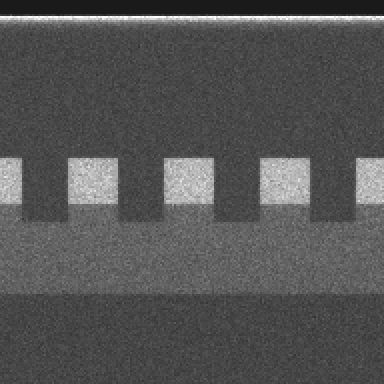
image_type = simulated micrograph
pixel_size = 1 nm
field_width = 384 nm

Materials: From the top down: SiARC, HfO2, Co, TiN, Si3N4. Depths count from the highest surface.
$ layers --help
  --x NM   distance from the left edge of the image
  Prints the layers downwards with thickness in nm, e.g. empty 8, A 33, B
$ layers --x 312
SiARC 206, Co 72, TiN 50, Si3N4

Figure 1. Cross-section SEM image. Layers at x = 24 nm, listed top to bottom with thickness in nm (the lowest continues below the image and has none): SiARC 206, Co 72, TiN 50, Si3N4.